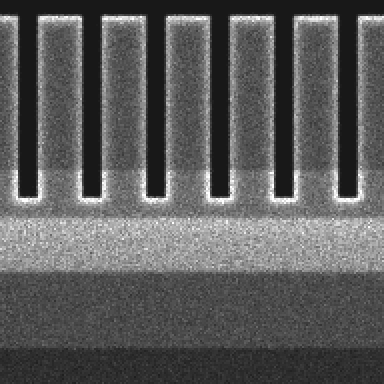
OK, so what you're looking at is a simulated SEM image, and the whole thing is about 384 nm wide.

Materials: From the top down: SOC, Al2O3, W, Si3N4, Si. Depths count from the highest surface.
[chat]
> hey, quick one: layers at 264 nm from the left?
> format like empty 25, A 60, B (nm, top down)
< SOC 154, Al2O3 48, W 54, Si3N4 76, Si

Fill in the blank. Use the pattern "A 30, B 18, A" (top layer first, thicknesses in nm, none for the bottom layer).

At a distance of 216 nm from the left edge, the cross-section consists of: empty 182, Al2O3 20, W 54, Si3N4 76, Si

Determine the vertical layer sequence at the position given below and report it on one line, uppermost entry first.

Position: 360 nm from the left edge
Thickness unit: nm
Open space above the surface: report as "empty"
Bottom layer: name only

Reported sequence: SOC 154, Al2O3 48, W 54, Si3N4 76, Si